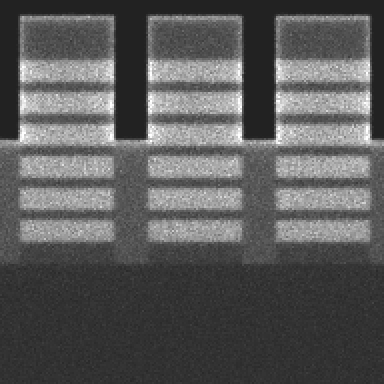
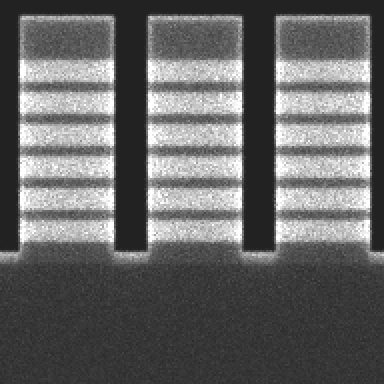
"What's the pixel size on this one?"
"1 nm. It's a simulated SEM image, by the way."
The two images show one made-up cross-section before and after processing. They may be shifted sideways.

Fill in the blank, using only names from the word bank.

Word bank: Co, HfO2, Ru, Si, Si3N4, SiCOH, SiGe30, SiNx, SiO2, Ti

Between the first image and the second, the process removed SiO2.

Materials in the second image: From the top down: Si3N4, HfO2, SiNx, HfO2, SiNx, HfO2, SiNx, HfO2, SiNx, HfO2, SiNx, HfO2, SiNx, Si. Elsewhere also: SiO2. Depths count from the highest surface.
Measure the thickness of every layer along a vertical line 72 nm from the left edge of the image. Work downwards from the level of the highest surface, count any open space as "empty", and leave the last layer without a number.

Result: Si3N4 44, HfO2 22, SiNx 10, HfO2 22, SiNx 10, HfO2 22, SiNx 10, HfO2 22, SiNx 10, HfO2 22, SiNx 10, HfO2 22, SiNx 22, Si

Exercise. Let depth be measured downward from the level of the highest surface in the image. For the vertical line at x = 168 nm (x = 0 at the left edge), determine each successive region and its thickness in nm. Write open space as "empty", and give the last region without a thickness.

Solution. Si3N4 44, HfO2 22, SiNx 10, HfO2 22, SiNx 10, HfO2 22, SiNx 10, HfO2 22, SiNx 10, HfO2 22, SiNx 10, HfO2 22, SiNx 22, Si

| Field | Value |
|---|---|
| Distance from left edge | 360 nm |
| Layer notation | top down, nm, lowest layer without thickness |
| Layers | Si3N4 44, HfO2 22, SiNx 10, HfO2 22, SiNx 10, HfO2 22, SiNx 10, HfO2 22, SiNx 10, HfO2 22, SiNx 10, HfO2 22, SiNx 22, Si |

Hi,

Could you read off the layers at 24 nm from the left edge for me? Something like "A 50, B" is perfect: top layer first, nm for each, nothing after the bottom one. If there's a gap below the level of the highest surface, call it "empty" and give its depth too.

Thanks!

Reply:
Si3N4 44, HfO2 22, SiNx 10, HfO2 22, SiNx 10, HfO2 22, SiNx 10, HfO2 22, SiNx 10, HfO2 22, SiNx 10, HfO2 22, SiNx 22, Si